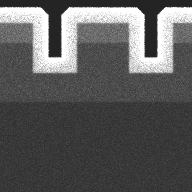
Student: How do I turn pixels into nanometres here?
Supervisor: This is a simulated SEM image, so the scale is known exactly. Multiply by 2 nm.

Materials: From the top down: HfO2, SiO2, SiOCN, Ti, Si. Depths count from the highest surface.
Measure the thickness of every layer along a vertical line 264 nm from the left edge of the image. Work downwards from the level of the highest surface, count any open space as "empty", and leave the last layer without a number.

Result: HfO2 130, SiOCN 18, Ti 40, Si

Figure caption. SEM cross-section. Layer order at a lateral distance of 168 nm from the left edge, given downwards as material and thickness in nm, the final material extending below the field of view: HfO2 30, SiO2 40, SiOCN 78, Ti 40, Si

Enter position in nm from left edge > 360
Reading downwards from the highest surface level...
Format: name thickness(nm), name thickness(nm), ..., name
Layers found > HfO2 30, SiO2 40, SiOCN 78, Ti 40, Si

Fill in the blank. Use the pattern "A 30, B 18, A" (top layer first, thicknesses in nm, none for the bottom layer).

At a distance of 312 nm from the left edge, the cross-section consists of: empty 100, HfO2 30, SiOCN 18, Ti 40, Si